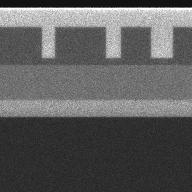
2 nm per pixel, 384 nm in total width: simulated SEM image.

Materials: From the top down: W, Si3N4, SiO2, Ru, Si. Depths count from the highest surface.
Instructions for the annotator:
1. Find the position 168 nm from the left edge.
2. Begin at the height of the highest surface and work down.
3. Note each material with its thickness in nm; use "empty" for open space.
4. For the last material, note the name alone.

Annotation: W 38, Si3N4 76, SiO2 70, Ru 34, Si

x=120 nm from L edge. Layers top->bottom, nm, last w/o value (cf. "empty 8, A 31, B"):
W 38, Si3N4 76, SiO2 70, Ru 34, Si